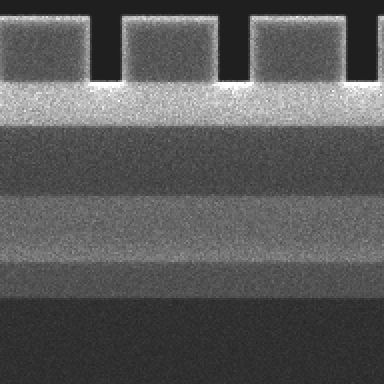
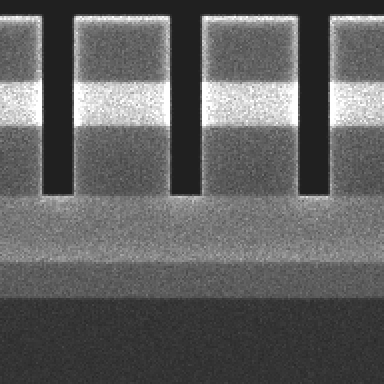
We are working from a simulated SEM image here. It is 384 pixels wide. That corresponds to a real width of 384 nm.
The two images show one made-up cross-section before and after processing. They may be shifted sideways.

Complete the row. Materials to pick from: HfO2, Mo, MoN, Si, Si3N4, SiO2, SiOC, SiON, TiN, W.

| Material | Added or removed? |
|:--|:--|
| HfO2 and TiN | removed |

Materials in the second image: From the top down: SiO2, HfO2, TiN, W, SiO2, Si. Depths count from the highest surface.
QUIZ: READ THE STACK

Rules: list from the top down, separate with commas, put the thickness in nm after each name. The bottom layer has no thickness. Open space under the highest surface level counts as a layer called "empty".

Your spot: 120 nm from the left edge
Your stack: SiO2 66, HfO2 44, TiN 70, W 66, SiO2 36, Si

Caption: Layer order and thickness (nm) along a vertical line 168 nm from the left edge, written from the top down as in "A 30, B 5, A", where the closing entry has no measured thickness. SiO2 66, HfO2 44, TiN 70, W 66, SiO2 36, Si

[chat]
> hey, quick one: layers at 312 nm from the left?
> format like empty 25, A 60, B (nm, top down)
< empty 180, W 66, SiO2 36, Si